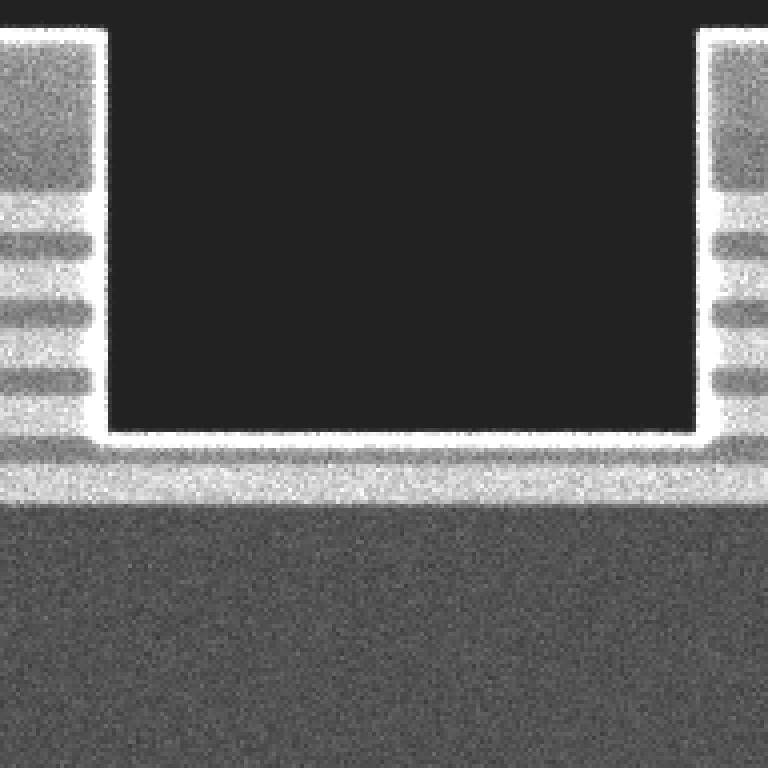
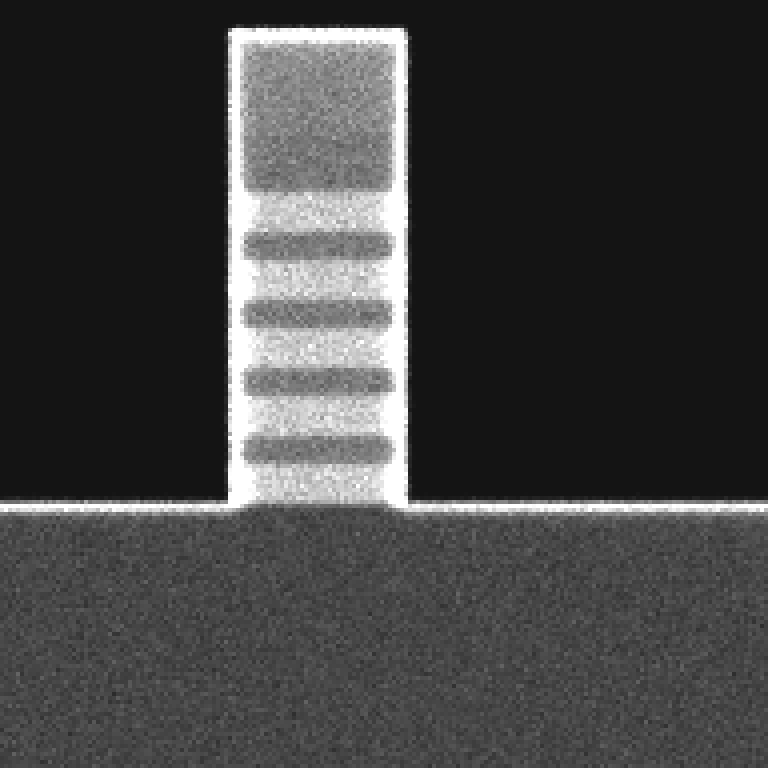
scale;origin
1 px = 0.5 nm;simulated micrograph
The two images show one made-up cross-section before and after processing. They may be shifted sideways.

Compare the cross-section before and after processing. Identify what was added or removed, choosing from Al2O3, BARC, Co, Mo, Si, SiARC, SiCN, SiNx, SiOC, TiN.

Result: Al2O3 and SiNx removed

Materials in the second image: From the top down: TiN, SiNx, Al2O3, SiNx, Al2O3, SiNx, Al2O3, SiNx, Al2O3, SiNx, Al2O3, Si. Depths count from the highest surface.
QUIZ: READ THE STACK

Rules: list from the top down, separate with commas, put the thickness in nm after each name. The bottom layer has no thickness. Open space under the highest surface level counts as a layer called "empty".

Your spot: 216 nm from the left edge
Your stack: empty 236, Si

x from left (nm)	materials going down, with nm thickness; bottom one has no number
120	TiN 50, SiNx 30, Al2O3 20, SiNx 14, Al2O3 20, SiNx 14, Al2O3 20, SiNx 14, Al2O3 20, SiNx 14, Al2O3 20, Si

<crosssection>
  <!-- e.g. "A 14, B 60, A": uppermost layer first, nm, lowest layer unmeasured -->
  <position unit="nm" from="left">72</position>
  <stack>empty 236, Si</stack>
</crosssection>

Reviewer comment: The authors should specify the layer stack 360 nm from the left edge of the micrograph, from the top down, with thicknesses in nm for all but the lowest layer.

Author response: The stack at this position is empty 236, Si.